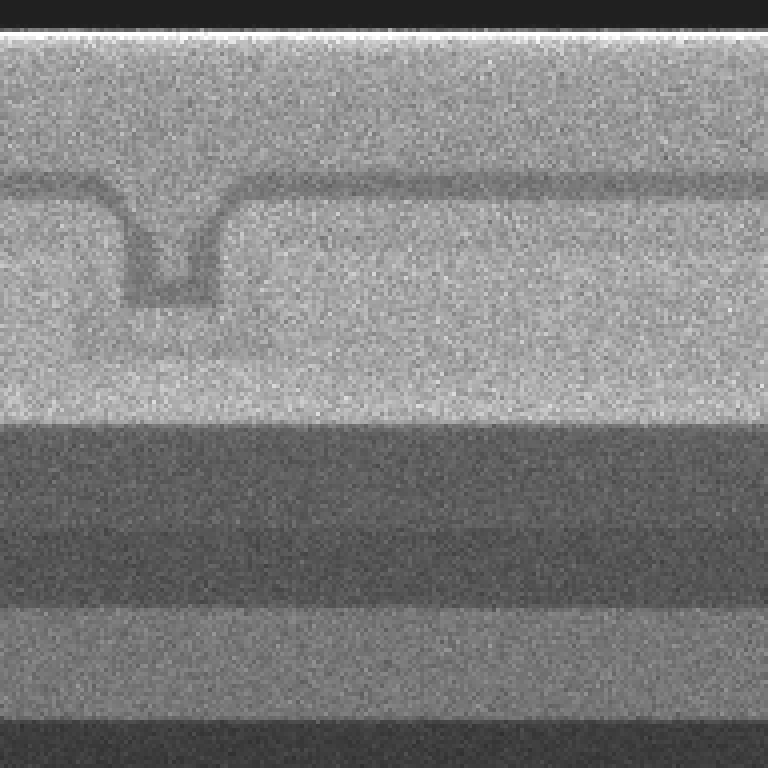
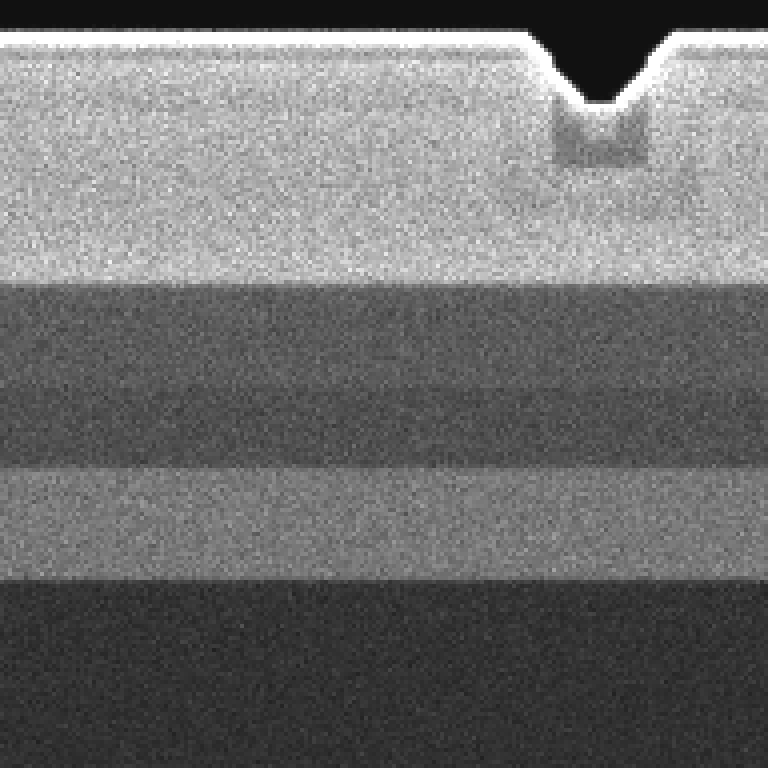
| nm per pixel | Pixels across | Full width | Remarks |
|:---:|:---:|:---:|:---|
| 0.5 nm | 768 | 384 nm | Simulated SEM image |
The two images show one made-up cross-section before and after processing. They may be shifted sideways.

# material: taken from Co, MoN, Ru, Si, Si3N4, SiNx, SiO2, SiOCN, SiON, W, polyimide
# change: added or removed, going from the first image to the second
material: Co
change: removed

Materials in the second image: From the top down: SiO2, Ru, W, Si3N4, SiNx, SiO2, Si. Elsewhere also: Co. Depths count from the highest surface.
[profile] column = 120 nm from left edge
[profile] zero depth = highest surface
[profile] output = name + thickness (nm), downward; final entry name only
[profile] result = SiO2 14, Ru 26, W 86, Si3N4 52, SiNx 40, SiO2 56, Si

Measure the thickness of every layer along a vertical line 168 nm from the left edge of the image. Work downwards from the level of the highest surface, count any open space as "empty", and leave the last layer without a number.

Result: SiO2 14, Ru 26, W 86, Si3N4 52, SiNx 40, SiO2 56, Si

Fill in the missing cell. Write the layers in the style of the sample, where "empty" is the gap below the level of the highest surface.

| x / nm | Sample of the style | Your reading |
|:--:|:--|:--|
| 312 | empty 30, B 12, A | empty 28, SiO2 40, Ru 26, W 32, Si3N4 52, SiNx 40, SiO2 56, Si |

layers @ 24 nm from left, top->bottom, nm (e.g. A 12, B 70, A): SiO2 14, Ru 26, W 86, Si3N4 52, SiNx 40, SiO2 56, Si